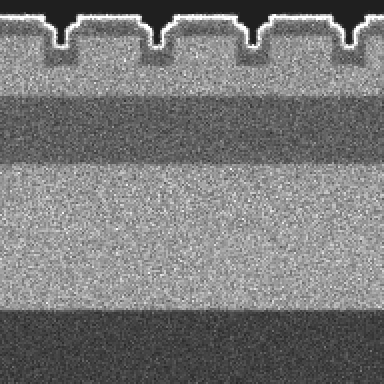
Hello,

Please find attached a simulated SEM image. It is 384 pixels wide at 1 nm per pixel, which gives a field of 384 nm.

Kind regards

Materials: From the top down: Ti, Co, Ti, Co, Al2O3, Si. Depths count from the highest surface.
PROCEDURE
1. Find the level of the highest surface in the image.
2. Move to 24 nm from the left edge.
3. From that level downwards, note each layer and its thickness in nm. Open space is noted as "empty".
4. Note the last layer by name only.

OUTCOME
Ti 20, Co 60, Ti 68, Co 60, Al2O3 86, Si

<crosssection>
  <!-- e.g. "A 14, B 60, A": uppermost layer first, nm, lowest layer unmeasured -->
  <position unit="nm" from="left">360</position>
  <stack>empty 8, Ti 42, Co 30, Ti 68, Co 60, Al2O3 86, Si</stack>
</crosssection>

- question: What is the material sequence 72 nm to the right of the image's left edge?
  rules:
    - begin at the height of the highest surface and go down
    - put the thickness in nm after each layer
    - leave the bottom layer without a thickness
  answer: empty 8, Ti 42, Co 30, Ti 68, Co 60, Al2O3 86, Si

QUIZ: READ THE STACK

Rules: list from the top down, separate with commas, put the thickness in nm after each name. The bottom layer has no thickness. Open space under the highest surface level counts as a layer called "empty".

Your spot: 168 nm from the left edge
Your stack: empty 8, Ti 42, Co 30, Ti 68, Co 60, Al2O3 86, Si